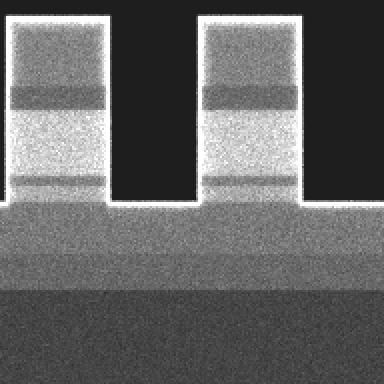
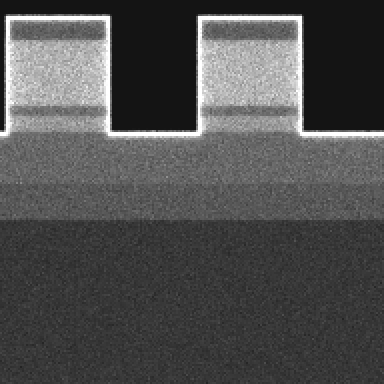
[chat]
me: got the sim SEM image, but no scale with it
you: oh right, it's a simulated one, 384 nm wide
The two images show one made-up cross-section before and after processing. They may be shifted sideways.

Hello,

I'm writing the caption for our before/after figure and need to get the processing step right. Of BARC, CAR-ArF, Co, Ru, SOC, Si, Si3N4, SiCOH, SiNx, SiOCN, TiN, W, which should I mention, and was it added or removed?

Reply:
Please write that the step removed SOC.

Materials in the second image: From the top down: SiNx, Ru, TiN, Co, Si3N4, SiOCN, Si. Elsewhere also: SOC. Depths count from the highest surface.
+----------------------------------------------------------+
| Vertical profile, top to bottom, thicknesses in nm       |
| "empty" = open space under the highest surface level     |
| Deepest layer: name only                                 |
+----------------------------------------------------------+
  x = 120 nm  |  empty 116, Si3N4 52, SiOCN 36, Si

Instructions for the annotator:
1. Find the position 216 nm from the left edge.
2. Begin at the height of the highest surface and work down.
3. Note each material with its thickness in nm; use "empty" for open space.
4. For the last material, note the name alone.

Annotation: SiNx 24, Ru 66, TiN 10, Co 16, Si3N4 52, SiOCN 36, Si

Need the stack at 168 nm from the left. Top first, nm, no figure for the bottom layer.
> empty 116, Si3N4 52, SiOCN 36, Si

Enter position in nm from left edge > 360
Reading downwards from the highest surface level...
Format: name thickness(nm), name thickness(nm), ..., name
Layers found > empty 116, Si3N4 52, SiOCN 36, Si